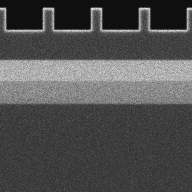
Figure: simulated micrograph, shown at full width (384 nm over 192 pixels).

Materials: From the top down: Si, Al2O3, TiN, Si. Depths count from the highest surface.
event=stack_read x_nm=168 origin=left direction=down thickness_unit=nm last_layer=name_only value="empty 44, Si 60, Al2O3 42, TiN 46, Si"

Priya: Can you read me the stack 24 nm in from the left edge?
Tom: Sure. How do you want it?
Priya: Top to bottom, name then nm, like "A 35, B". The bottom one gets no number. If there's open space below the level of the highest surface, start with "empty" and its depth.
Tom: empty 44, Si 60, Al2O3 42, TiN 46, Si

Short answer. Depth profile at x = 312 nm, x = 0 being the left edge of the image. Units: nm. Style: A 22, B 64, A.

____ empty 44, Si 60, Al2O3 42, TiN 46, Si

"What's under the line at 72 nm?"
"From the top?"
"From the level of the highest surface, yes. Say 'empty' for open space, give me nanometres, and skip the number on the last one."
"empty 44, Si 60, Al2O3 42, TiN 46, Si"